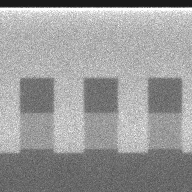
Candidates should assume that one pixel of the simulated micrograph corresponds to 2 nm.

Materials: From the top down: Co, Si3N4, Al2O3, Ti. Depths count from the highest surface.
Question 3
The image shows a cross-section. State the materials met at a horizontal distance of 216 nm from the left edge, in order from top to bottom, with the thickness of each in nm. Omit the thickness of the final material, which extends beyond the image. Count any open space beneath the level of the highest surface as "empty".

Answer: Co 140, Si3N4 70, Al2O3 72, Ti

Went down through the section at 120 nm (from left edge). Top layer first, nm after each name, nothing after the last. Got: Co 290, Ti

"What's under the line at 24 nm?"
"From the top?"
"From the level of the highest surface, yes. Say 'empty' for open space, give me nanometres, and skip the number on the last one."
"Co 290, Ti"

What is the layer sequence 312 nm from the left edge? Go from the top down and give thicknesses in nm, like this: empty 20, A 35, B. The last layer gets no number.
Co 140, Si3N4 70, Al2O3 72, Ti